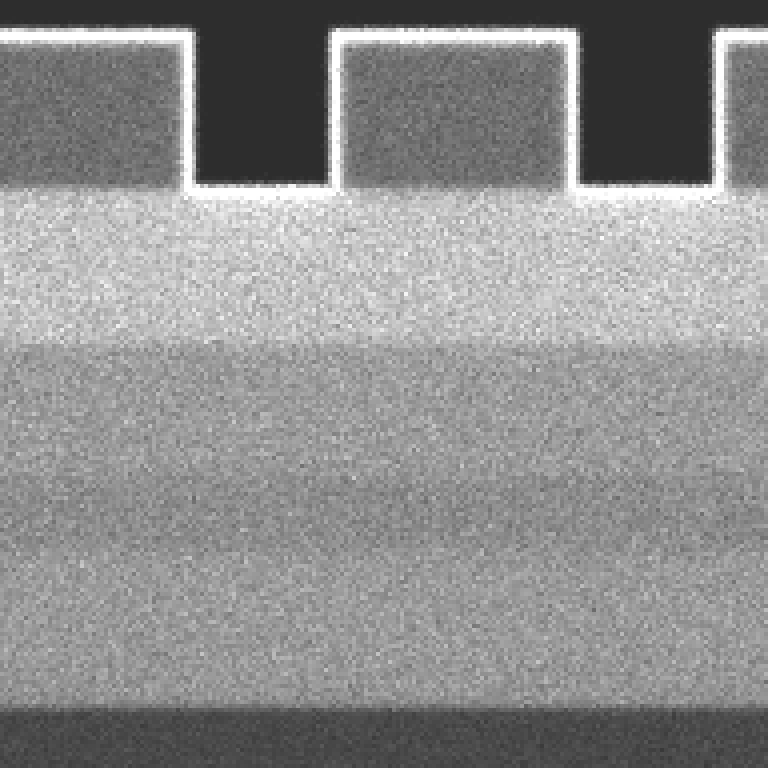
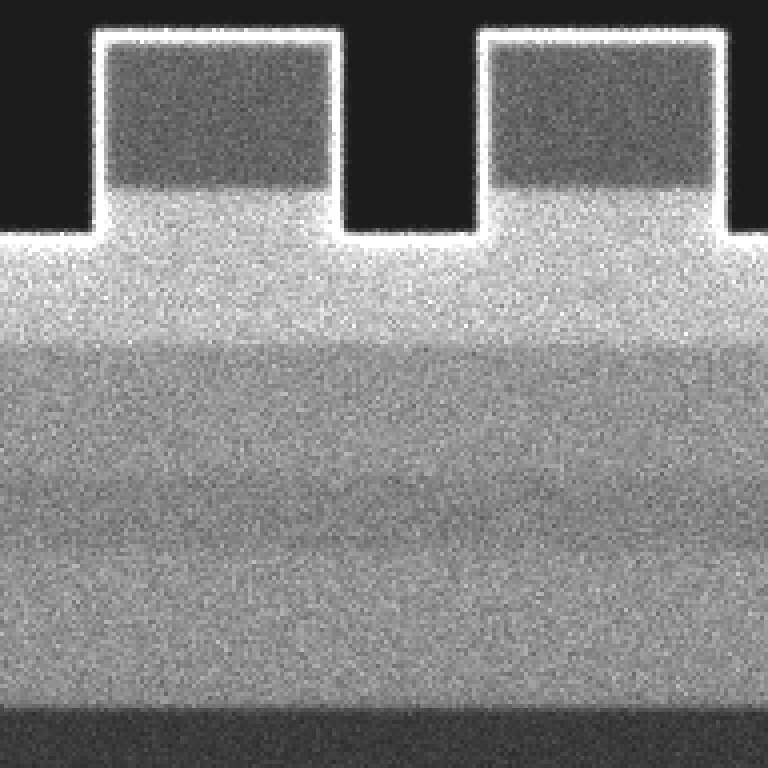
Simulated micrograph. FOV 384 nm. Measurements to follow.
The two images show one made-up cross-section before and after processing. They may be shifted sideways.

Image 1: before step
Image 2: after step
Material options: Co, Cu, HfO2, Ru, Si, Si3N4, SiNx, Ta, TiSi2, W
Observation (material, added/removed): W, removed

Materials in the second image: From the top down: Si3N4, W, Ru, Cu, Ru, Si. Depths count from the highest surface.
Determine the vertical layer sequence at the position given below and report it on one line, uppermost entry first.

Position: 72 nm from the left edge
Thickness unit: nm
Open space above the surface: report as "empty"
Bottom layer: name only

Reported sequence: Si3N4 78, W 78, Ru 66, Cu 38, Ru 78, Si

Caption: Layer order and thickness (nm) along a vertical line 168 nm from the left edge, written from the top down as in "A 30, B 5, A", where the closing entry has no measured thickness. Si3N4 78, W 78, Ru 66, Cu 38, Ru 78, Si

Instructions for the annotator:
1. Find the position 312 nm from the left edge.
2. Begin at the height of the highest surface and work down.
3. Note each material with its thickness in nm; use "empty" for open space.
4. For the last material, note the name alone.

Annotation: Si3N4 78, W 78, Ru 66, Cu 38, Ru 78, Si